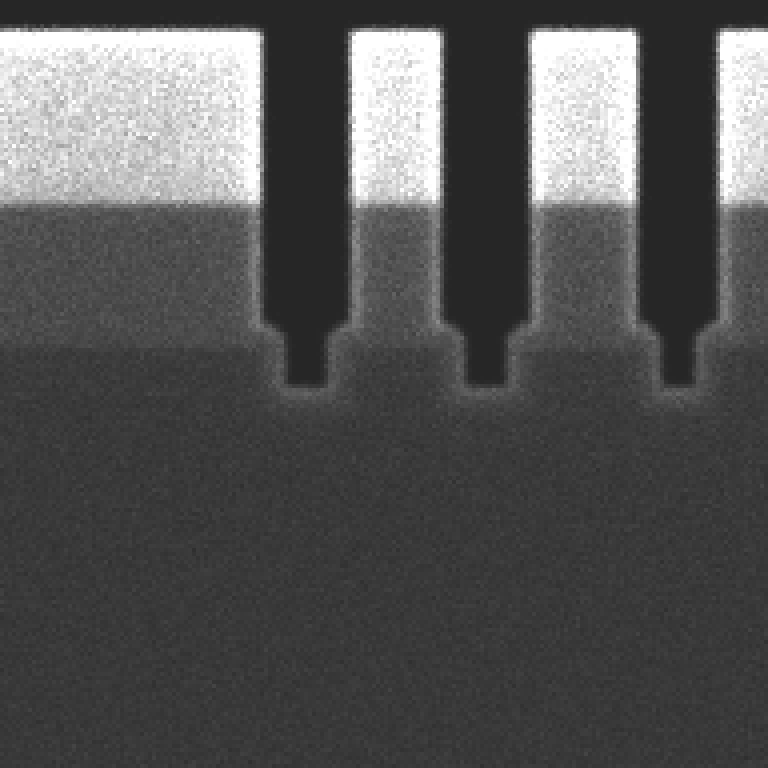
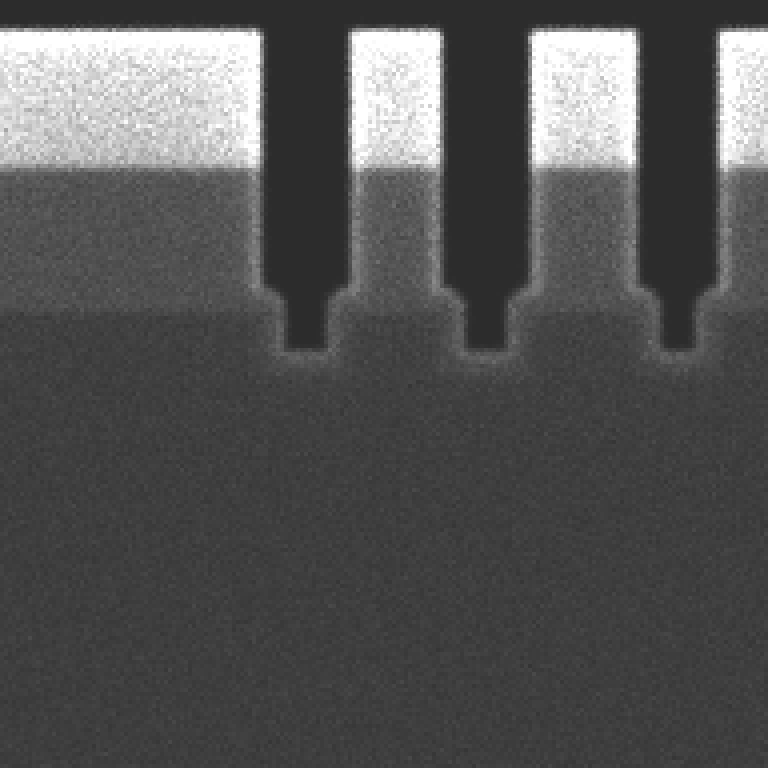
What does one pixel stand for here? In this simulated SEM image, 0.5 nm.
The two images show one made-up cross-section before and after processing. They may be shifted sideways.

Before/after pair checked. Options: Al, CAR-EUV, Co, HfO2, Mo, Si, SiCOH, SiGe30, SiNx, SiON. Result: removed HfO2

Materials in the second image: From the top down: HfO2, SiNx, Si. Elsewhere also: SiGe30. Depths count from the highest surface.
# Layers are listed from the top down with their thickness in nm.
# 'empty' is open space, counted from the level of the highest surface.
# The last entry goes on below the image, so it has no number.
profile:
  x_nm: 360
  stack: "HfO2 68, SiNx 72, Si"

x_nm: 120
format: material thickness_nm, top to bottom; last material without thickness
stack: HfO2 68, SiNx 72, Si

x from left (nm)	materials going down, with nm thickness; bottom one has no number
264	empty 128, SiGe30 44, Si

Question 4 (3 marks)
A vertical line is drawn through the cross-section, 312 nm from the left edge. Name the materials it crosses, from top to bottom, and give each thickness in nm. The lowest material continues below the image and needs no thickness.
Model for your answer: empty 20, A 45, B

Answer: HfO2 68, SiNx 72, Si